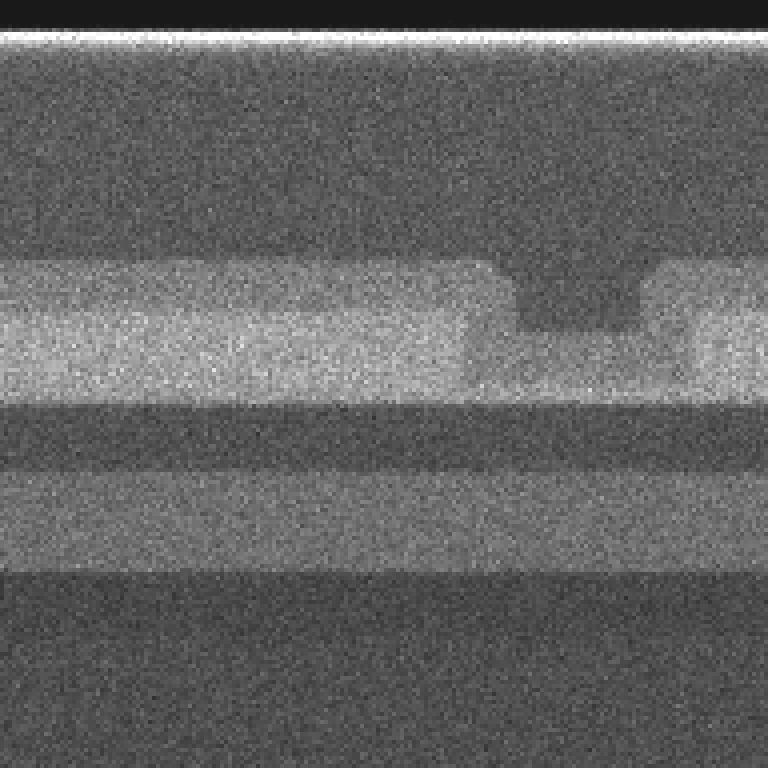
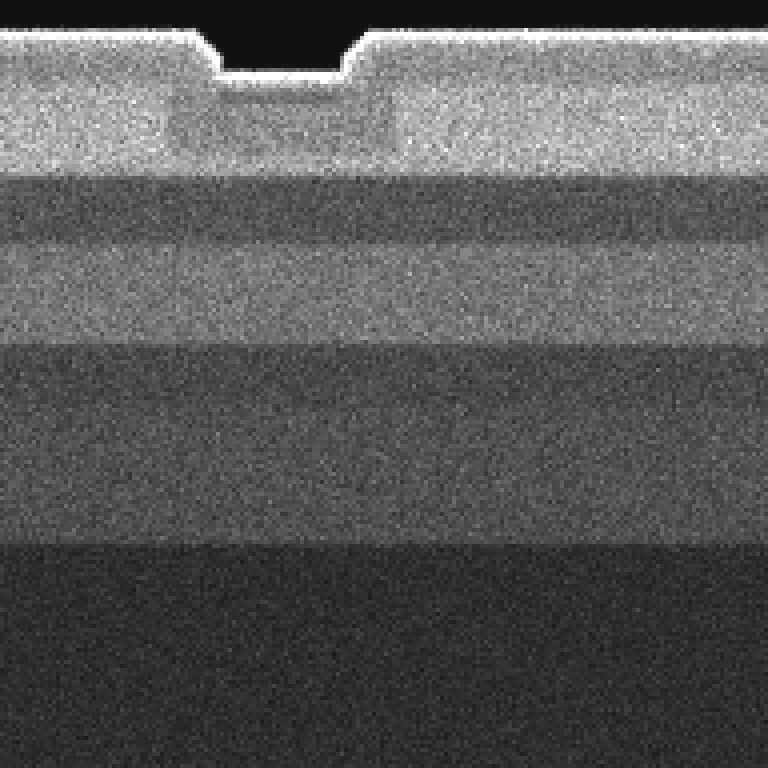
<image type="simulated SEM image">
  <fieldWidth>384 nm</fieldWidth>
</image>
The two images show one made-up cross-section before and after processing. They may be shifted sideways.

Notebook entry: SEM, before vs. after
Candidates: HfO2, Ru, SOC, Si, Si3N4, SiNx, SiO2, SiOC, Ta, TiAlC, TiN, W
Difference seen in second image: SOC removed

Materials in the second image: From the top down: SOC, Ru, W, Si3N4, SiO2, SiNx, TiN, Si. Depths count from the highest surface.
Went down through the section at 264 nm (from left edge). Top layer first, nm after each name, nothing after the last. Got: Ru 26, W 46, Si3N4 34, SiO2 50, SiNx 32, TiN 68, Si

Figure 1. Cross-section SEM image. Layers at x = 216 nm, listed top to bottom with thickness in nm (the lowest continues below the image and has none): Ru 26, W 46, Si3N4 34, SiO2 50, SiNx 32, TiN 68, Si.